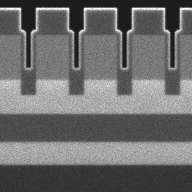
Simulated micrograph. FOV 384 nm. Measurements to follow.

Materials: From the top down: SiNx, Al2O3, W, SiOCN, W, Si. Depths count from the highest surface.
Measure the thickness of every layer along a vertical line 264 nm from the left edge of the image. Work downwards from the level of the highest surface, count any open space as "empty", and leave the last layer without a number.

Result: SiNx 54, Al2O3 90, W 68, SiOCN 56, W 46, Si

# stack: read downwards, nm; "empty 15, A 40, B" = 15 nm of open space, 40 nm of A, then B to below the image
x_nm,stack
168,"SiNx 54, Al2O3 90, W 68, SiOCN 56, W 46, Si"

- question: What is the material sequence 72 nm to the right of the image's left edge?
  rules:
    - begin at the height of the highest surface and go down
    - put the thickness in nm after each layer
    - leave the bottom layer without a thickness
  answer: SiNx 54, Al2O3 90, W 68, SiOCN 56, W 46, Si